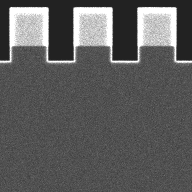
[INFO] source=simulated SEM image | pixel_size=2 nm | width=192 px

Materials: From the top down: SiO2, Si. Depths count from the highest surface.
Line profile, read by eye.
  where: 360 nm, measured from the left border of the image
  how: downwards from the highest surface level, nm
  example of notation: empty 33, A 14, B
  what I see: empty 106, Si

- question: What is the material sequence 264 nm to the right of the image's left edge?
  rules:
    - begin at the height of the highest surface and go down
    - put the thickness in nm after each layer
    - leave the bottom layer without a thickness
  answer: empty 106, Si